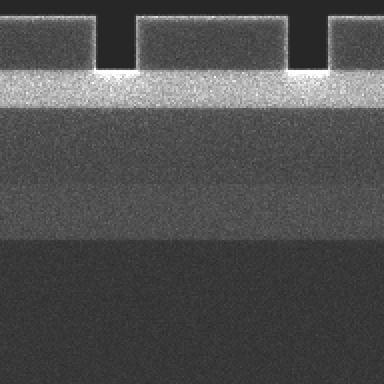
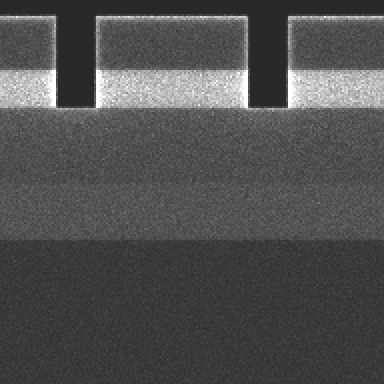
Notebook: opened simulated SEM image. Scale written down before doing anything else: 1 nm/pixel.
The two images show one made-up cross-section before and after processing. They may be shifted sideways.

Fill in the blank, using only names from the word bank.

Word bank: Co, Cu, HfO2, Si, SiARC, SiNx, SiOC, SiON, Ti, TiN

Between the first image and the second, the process removed HfO2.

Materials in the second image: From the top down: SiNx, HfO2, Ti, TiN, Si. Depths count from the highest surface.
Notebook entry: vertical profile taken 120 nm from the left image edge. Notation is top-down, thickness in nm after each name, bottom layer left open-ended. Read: SiNx 54, HfO2 38, Ti 76, TiN 56, Si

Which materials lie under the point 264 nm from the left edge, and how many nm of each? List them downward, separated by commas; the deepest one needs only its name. empty 92, Ti 76, TiN 56, Si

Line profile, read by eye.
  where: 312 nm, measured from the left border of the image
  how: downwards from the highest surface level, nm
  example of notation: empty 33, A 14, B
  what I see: SiNx 54, HfO2 38, Ti 76, TiN 56, Si